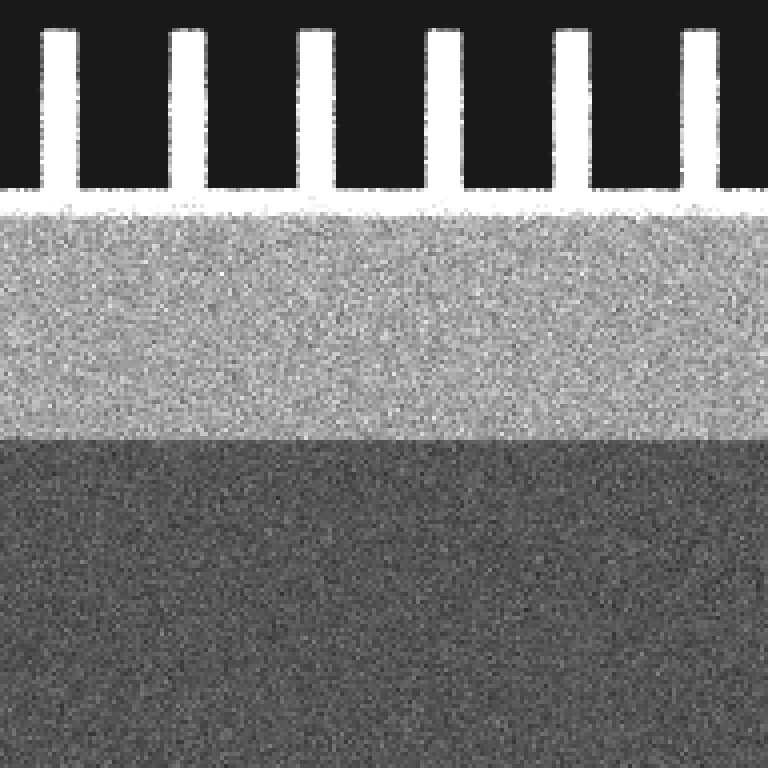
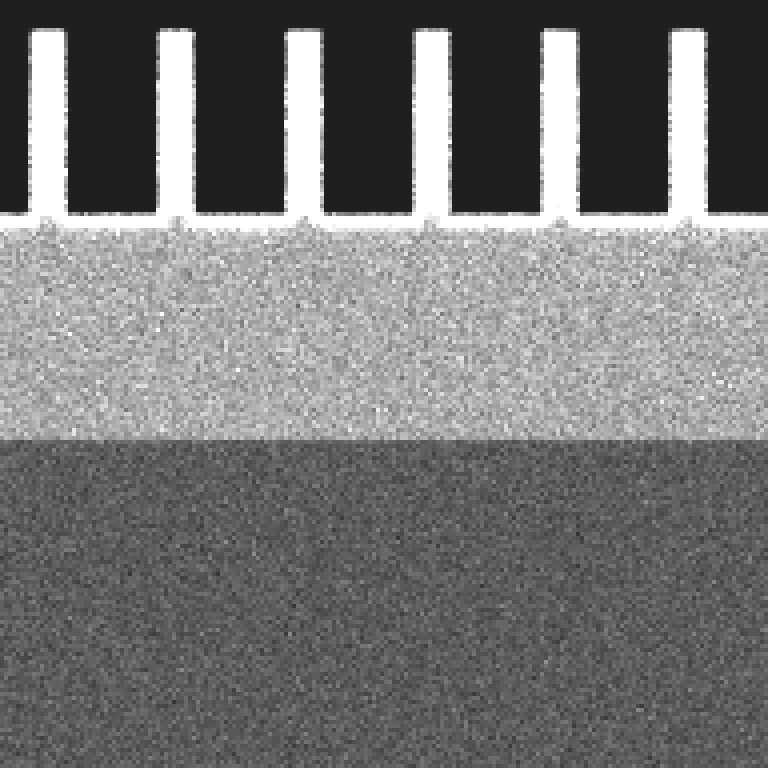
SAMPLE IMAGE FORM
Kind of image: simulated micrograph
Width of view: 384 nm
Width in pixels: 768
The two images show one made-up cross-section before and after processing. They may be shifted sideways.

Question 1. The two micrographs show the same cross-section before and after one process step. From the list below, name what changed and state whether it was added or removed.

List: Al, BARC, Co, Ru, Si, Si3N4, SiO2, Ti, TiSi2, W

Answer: Co, removed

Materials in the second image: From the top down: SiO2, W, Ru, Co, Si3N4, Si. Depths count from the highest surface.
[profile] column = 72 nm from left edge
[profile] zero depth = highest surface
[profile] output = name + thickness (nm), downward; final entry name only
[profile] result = empty 92, Si3N4 112, Si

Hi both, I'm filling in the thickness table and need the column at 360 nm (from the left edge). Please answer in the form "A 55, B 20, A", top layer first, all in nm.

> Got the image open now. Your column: empty 92, Si3N4 112, Si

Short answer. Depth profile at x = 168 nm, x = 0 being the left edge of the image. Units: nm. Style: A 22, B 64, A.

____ empty 92, Si3N4 112, Si